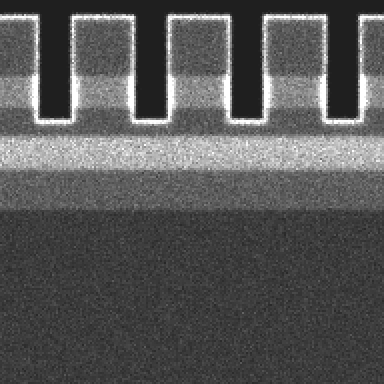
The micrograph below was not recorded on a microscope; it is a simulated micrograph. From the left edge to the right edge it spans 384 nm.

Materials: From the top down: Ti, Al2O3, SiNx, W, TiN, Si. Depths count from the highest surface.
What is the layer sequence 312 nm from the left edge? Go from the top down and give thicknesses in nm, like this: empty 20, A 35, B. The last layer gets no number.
Ti 60, Al2O3 32, SiNx 28, W 34, TiN 40, Si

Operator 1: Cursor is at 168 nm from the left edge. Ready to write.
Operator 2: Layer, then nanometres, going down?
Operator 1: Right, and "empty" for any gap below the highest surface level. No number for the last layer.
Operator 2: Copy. Ti 60, Al2O3 32, SiNx 28, W 34, TiN 40, Si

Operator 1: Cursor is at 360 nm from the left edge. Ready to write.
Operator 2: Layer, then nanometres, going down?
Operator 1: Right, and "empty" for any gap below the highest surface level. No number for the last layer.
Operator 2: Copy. Ti 60, Al2O3 32, SiNx 28, W 34, TiN 40, Si